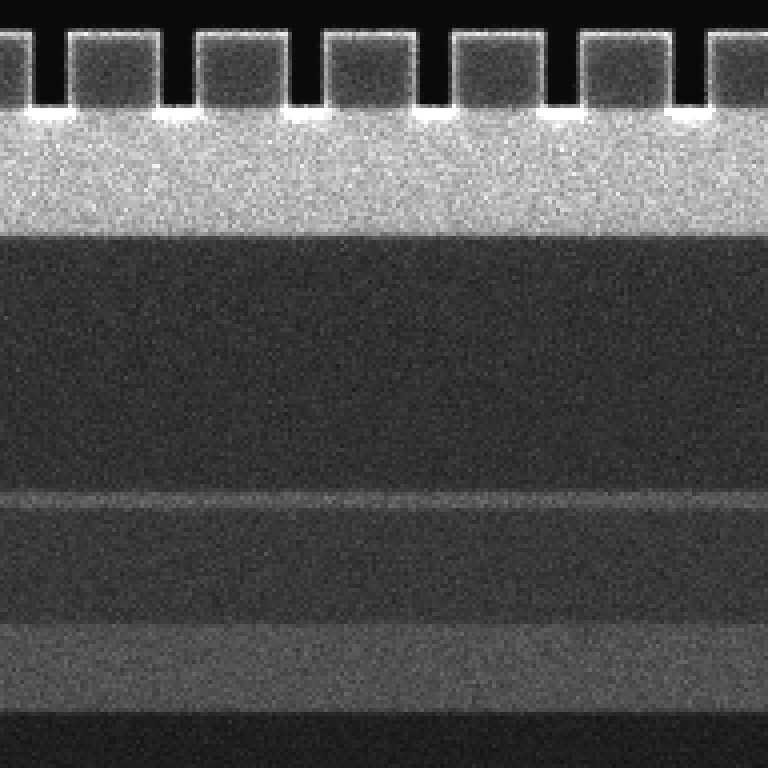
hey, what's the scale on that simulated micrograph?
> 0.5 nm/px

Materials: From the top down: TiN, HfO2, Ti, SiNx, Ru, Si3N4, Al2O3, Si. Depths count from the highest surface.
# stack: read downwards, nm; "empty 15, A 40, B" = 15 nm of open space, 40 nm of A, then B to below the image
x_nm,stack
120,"TiN 38, HfO2 64, Ti 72, SiNx 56, Ru 8, Si3N4 58, Al2O3 44, Si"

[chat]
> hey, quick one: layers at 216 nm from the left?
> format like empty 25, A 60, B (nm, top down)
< empty 38, HfO2 64, Ti 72, SiNx 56, Ru 8, Si3N4 58, Al2O3 44, Si